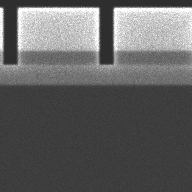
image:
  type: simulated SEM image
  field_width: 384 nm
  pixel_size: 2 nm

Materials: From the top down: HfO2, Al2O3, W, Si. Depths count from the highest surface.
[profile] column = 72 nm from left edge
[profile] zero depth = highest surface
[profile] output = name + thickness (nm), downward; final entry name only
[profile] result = HfO2 86, Al2O3 28, W 40, Si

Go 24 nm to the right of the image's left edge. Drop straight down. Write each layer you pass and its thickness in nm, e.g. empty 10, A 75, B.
empty 114, W 40, Si